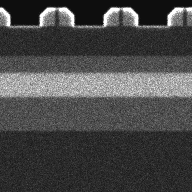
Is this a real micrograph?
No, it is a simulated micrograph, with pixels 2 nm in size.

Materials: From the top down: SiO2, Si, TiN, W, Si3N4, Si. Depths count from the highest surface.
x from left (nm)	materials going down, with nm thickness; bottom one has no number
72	empty 36, Si 60, TiN 34, W 48, Si3N4 68, Si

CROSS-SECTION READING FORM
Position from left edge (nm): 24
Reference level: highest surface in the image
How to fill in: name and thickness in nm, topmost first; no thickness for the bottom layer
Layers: empty 36, Si 60, TiN 34, W 48, Si3N4 68, Si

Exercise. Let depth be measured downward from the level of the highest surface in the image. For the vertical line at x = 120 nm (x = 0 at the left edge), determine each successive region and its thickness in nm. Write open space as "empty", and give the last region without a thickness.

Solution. SiO2 36, Si 60, TiN 34, W 48, Si3N4 68, Si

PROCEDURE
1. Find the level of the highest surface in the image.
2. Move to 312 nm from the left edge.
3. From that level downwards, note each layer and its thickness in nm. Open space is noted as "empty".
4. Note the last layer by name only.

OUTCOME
empty 36, Si 60, TiN 34, W 48, Si3N4 68, Si